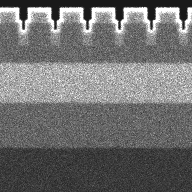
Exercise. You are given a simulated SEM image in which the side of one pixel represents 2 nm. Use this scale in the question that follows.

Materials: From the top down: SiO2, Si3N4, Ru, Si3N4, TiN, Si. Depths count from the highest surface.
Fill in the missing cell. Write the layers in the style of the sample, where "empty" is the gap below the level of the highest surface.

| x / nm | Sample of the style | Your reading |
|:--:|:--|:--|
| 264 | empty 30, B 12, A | SiO2 30, Si3N4 80, Ru 80, Si3N4 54, TiN 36, Si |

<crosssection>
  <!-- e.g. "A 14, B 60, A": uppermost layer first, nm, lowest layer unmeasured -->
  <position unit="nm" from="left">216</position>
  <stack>SiO2 30, Si3N4 80, Ru 80, Si3N4 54, TiN 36, Si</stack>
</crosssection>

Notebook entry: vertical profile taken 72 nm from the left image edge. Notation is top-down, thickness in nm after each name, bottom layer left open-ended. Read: SiO2 30, Si3N4 80, Ru 80, Si3N4 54, TiN 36, Si